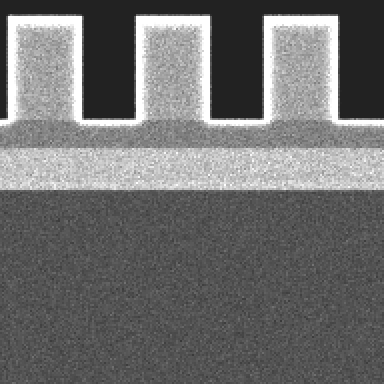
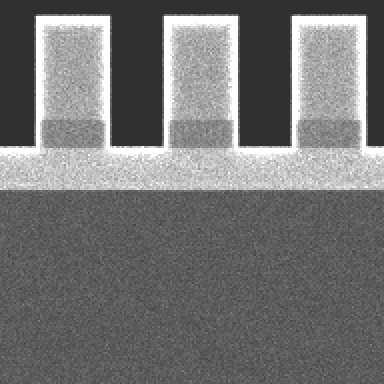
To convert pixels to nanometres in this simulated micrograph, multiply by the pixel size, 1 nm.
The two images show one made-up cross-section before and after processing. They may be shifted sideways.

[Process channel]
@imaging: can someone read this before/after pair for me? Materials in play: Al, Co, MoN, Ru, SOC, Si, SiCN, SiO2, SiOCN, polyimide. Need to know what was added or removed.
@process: SiOCN removed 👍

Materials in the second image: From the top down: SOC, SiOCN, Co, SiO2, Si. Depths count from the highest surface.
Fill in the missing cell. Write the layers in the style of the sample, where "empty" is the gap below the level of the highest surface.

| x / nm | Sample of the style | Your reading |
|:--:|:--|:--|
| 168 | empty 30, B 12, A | SOC 104, SiOCN 28, Co 34, SiO2 8, Si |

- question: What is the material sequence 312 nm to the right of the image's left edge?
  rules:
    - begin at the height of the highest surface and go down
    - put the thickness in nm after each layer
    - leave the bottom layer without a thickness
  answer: SOC 104, SiOCN 28, Co 34, SiO2 8, Si